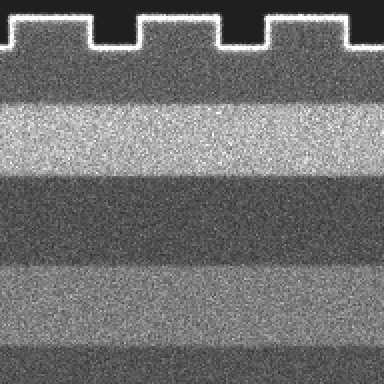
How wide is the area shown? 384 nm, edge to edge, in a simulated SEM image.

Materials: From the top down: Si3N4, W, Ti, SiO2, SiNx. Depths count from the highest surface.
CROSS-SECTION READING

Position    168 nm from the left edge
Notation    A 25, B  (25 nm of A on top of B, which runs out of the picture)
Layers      Si3N4 88, W 72, Ti 90, SiO2 80, SiNx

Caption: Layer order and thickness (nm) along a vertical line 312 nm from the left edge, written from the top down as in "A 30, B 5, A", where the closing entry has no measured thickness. Si3N4 88, W 72, Ti 90, SiO2 80, SiNx